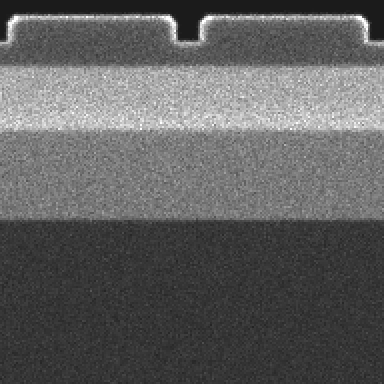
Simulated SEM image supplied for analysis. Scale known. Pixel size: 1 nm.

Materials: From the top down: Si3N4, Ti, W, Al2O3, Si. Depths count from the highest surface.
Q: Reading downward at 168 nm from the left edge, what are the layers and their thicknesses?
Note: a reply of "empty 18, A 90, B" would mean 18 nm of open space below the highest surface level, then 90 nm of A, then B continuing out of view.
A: Si3N4 26, Ti 24, W 64, Al2O3 90, Si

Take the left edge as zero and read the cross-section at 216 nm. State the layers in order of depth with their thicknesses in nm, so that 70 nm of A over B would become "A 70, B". Ti 50, W 64, Al2O3 90, Si